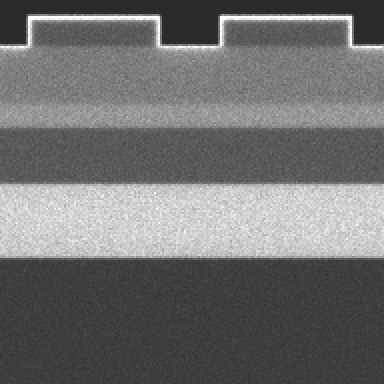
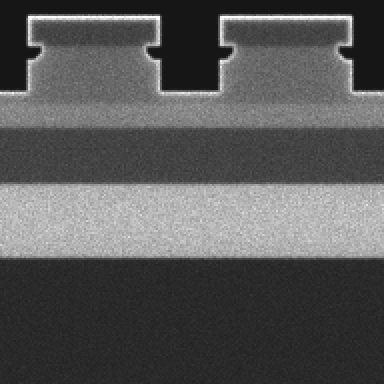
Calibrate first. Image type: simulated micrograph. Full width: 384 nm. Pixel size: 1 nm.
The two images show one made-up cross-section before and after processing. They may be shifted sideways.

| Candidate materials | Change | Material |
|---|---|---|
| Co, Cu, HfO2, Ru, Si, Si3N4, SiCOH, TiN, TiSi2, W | removed | Ru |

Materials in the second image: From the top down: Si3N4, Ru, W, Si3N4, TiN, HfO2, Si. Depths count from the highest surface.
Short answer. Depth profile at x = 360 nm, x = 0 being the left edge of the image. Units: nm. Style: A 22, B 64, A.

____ empty 76, Ru 12, W 24, Si3N4 16, TiN 40, HfO2 74, Si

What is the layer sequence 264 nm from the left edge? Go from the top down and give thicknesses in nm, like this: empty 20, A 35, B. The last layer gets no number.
Si3N4 30, Ru 58, W 24, Si3N4 16, TiN 40, HfO2 74, Si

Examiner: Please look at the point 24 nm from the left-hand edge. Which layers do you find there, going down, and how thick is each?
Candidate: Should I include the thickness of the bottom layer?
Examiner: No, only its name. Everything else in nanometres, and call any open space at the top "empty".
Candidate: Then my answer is empty 76, Ru 12, W 24, Si3N4 16, TiN 40, HfO2 74, Si